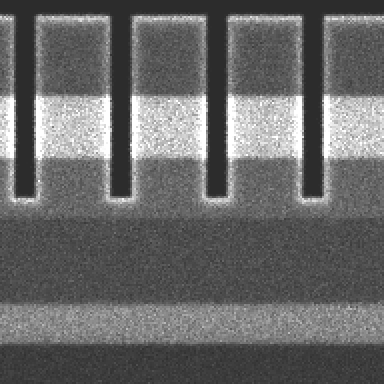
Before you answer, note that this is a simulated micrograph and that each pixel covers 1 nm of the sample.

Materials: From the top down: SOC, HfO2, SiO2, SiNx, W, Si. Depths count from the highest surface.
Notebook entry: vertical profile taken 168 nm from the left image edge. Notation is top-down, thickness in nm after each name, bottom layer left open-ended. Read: SOC 80, HfO2 62, SiO2 60, SiNx 86, W 40, Si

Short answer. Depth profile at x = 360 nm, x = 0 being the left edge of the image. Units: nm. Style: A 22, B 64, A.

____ SOC 80, HfO2 62, SiO2 60, SiNx 86, W 40, Si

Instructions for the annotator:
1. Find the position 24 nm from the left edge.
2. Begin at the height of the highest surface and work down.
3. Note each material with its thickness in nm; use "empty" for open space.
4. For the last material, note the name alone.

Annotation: empty 182, SiO2 20, SiNx 86, W 40, Si